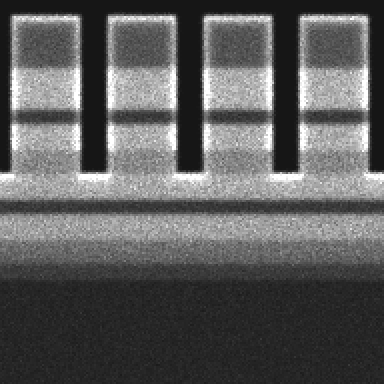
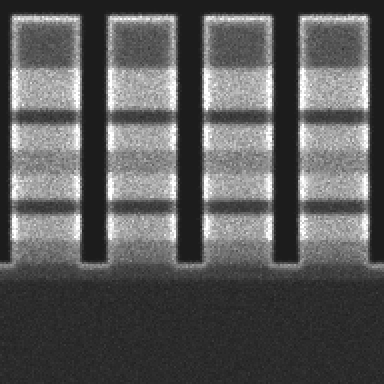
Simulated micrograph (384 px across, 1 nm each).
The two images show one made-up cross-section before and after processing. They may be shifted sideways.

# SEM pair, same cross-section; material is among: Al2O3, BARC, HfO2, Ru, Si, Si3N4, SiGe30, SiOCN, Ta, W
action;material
removed;HfO2 and Ru and SiOCN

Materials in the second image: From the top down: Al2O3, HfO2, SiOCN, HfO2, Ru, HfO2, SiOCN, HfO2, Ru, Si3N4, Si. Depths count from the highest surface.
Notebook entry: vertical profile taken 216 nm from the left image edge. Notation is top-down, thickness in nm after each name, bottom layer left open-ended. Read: Al2O3 52, HfO2 42, SiOCN 14, HfO2 26, Ru 24, HfO2 26, SiOCN 14, HfO2 26, Ru 24, Si3N4 16, Si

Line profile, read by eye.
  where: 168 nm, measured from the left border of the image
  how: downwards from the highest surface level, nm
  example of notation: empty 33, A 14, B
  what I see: Al2O3 52, HfO2 42, SiOCN 14, HfO2 26, Ru 24, HfO2 26, SiOCN 14, HfO2 26, Ru 24, Si3N4 16, Si